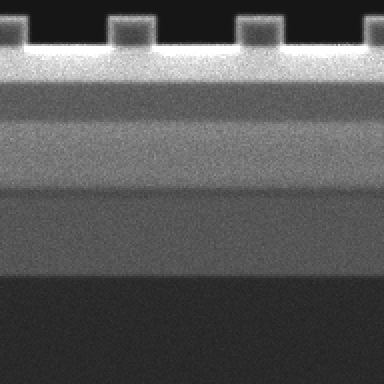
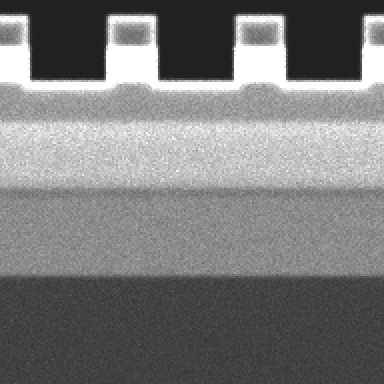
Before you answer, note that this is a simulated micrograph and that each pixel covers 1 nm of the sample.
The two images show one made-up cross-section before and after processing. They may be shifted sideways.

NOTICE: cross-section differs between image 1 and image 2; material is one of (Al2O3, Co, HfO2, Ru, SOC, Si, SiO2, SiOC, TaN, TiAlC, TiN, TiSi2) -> removed: HfO2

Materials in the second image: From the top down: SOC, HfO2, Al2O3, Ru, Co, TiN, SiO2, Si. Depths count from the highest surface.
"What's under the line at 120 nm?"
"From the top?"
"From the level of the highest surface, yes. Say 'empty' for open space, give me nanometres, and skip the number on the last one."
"SOC 30, HfO2 36, Al2O3 40, Ru 56, Co 10, TiN 10, SiO2 78, Si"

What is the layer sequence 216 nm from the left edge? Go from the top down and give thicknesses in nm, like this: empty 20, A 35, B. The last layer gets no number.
empty 66, Al2O3 40, Ru 56, Co 10, TiN 10, SiO2 78, Si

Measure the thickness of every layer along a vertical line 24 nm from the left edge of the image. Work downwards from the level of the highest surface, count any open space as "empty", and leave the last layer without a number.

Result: SOC 30, HfO2 36, Al2O3 40, Ru 56, Co 10, TiN 10, SiO2 78, Si